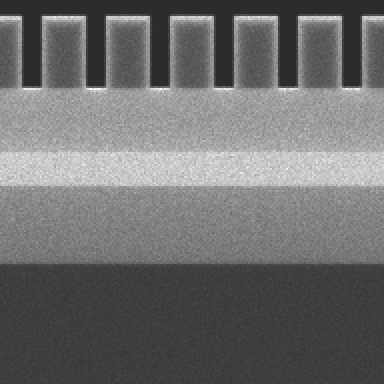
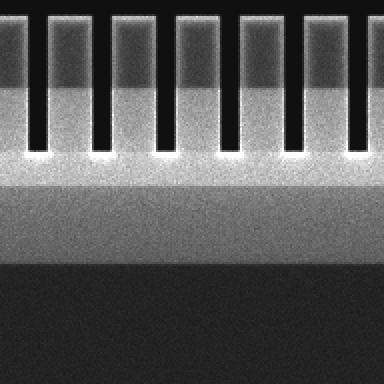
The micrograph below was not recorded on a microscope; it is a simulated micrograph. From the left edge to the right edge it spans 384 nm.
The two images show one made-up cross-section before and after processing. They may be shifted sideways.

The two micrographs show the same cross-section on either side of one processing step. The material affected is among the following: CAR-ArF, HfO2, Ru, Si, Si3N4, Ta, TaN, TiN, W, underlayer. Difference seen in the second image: W removed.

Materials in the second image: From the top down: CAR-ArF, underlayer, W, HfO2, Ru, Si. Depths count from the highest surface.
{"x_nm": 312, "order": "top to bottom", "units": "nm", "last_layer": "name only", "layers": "CAR-ArF 32, underlayer 40, W 64, HfO2 34, Ru 78, Si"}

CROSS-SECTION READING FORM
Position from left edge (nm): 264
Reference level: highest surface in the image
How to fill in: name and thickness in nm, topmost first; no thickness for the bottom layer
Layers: CAR-ArF 32, underlayer 40, W 64, HfO2 34, Ru 78, Si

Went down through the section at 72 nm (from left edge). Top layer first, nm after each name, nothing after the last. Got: CAR-ArF 32, underlayer 40, W 64, HfO2 34, Ru 78, Si